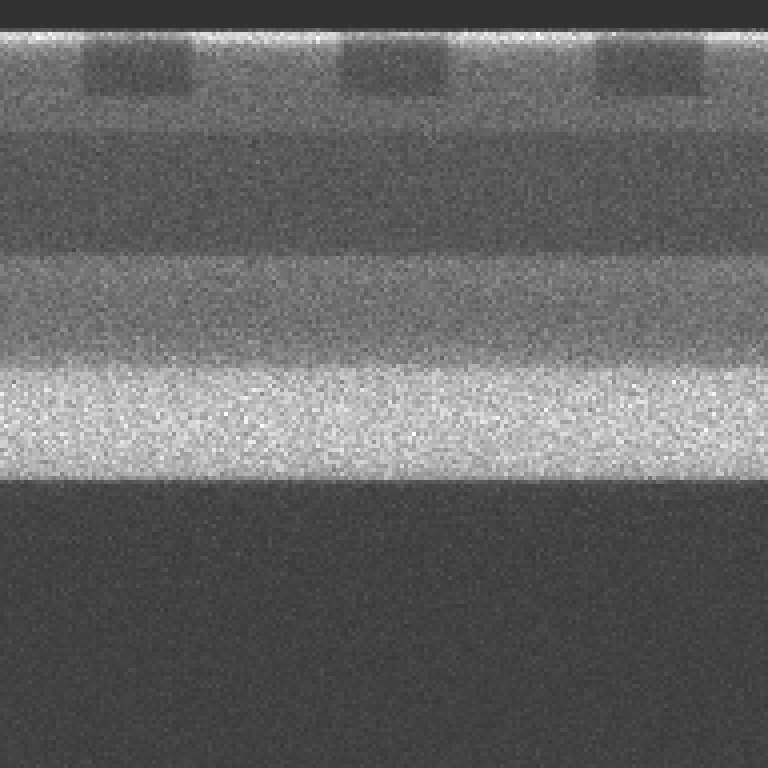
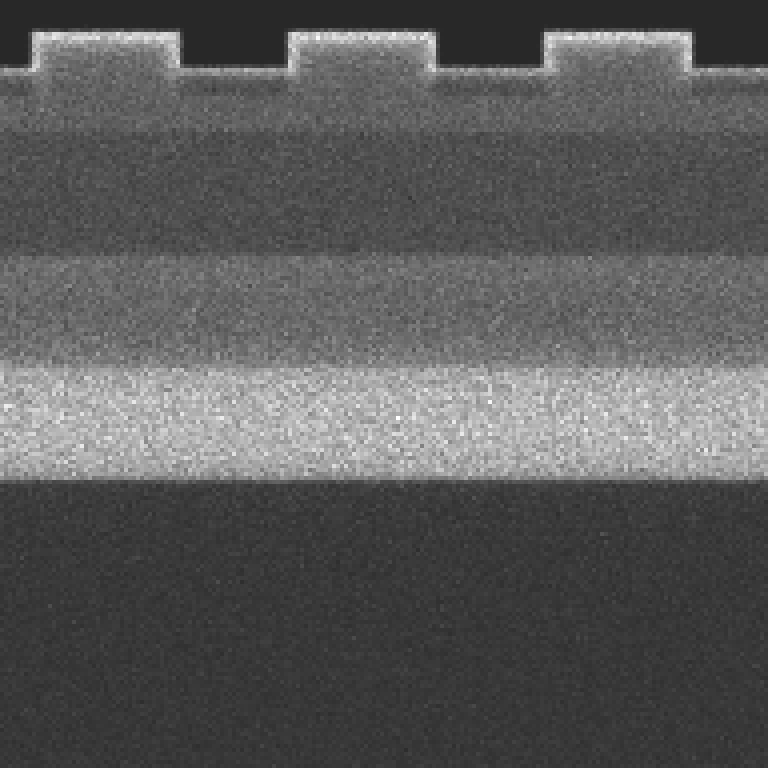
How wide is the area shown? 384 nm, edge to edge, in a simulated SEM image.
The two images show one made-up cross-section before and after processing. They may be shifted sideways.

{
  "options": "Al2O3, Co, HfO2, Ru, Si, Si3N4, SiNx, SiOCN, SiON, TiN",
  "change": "removed",
  "material": "SiNx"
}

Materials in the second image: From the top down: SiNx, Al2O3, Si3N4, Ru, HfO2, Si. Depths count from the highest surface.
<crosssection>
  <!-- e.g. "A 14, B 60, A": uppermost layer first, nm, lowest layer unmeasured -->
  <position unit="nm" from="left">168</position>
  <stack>Al2O3 50, Si3N4 62, Ru 56, HfO2 56, Si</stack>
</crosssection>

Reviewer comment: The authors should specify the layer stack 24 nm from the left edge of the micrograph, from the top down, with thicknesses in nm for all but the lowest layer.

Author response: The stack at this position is Al2O3 50, Si3N4 62, Ru 56, HfO2 56, Si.